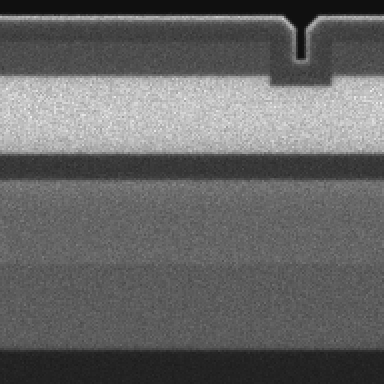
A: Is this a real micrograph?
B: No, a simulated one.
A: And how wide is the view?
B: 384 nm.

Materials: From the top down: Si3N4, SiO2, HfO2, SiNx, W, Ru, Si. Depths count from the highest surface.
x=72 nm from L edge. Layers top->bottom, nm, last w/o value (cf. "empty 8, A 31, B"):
Si3N4 26, SiO2 34, HfO2 78, SiNx 26, W 84, Ru 86, Si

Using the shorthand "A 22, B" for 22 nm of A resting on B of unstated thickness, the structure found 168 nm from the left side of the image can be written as Si3N4 26, SiO2 34, HfO2 78, SiNx 26, W 84, Ru 86, Si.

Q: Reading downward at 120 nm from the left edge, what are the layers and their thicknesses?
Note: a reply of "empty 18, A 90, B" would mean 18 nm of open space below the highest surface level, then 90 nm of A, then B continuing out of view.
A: Si3N4 26, SiO2 34, HfO2 78, SiNx 26, W 84, Ru 86, Si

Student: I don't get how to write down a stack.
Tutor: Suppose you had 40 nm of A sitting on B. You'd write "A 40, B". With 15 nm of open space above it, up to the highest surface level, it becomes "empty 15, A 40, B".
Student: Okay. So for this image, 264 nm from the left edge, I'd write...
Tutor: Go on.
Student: Si3N4 26, SiO2 34, HfO2 78, SiNx 26, W 84, Ru 86, Si